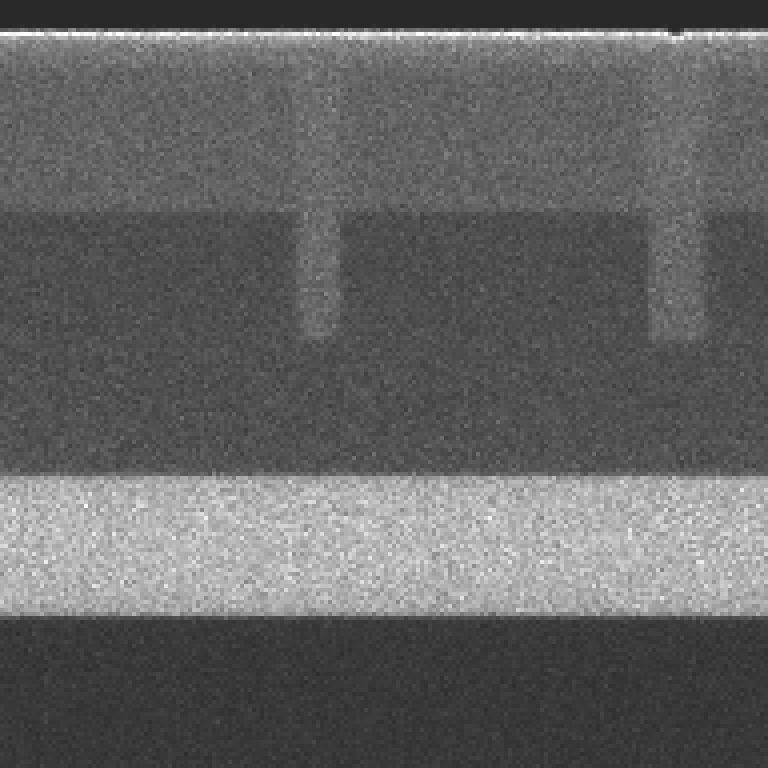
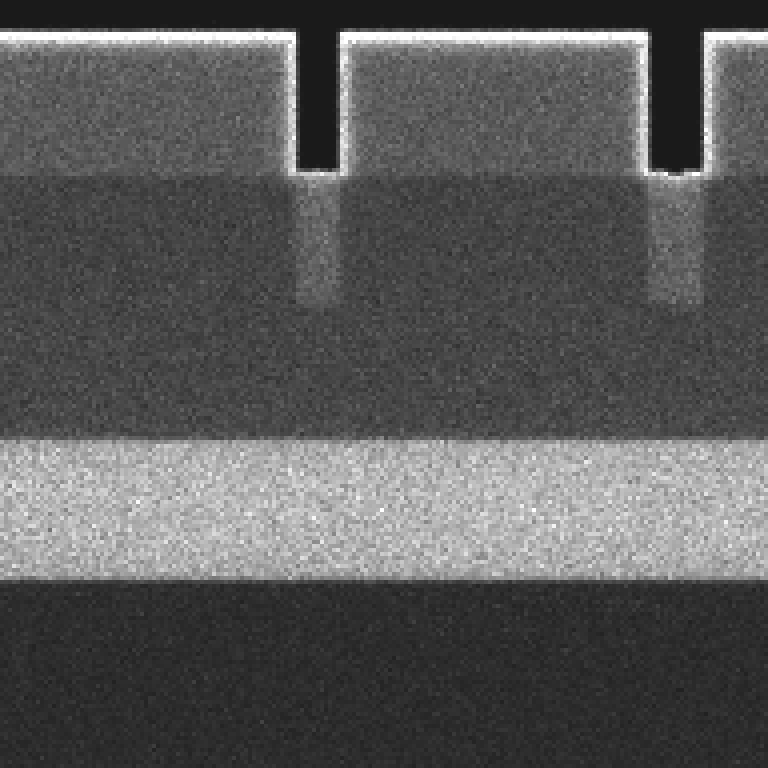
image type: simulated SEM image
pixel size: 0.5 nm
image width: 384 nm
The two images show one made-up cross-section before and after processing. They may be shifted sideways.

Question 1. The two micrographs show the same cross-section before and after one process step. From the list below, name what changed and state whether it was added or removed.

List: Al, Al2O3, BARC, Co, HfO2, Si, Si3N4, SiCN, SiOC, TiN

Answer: Co, removed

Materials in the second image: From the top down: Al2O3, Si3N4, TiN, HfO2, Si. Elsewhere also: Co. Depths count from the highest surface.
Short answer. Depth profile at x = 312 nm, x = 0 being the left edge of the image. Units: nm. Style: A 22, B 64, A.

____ Al2O3 72, Si3N4 52, TiN 80, HfO2 70, Si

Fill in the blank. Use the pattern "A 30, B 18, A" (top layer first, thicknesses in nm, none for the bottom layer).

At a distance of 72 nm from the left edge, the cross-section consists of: Al2O3 72, Si3N4 52, TiN 80, HfO2 70, Si